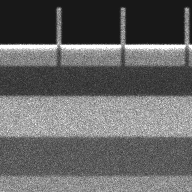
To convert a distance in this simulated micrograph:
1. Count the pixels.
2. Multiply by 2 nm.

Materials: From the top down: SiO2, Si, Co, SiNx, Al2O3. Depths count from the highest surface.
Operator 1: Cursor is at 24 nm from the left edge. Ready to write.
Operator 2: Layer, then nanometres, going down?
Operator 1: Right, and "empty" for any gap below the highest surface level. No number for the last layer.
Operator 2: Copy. empty 74, SiO2 42, Si 60, Co 82, SiNx 78, Al2O3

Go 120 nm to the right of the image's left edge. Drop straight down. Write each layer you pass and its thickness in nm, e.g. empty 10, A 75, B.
Si 176, Co 82, SiNx 78, Al2O3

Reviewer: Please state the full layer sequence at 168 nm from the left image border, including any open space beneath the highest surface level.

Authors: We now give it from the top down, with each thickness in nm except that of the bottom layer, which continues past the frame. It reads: empty 74, SiO2 42, Si 60, Co 82, SiNx 78, Al2O3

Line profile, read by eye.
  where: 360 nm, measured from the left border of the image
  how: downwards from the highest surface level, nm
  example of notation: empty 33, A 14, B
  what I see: empty 74, SiO2 42, Si 60, Co 82, SiNx 78, Al2O3